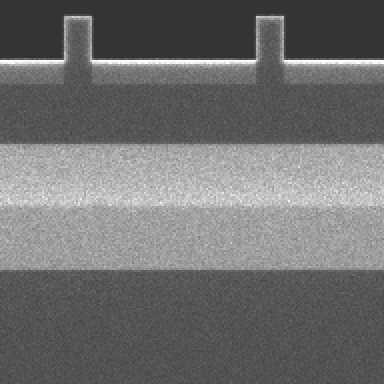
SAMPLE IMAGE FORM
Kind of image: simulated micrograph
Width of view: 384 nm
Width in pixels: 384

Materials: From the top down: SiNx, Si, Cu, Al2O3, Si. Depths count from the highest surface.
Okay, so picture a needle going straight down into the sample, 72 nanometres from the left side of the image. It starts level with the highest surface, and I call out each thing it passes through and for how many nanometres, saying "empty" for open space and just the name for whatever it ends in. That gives Si 128, Cu 62, Al2O3 64, Si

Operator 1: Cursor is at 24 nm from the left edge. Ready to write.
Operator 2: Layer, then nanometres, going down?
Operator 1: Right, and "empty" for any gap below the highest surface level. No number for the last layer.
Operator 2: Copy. empty 44, SiNx 24, Si 60, Cu 62, Al2O3 64, Si